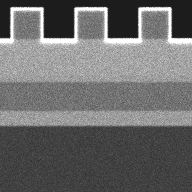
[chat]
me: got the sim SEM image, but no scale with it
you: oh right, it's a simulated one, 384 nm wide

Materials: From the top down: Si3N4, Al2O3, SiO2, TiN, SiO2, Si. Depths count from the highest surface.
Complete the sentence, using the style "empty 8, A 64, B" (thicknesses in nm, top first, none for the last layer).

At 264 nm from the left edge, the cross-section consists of empty 62, Al2O3 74, SiO2 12, TiN 58, SiO2 30, Si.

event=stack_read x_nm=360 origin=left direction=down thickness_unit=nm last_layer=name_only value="empty 62, Al2O3 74, SiO2 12, TiN 58, SiO2 30, Si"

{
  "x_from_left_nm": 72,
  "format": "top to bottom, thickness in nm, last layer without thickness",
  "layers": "Si3N4 62, Al2O3 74, SiO2 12, TiN 58, SiO2 30, Si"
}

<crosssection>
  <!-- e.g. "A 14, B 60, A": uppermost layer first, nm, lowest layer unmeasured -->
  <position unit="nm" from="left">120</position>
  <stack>empty 62, Al2O3 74, SiO2 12, TiN 58, SiO2 30, Si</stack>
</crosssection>